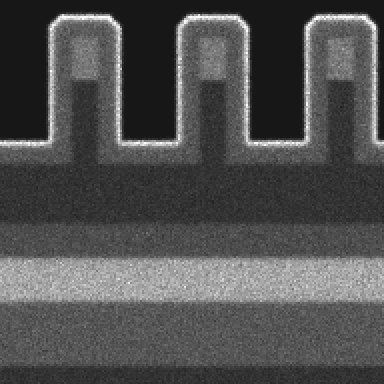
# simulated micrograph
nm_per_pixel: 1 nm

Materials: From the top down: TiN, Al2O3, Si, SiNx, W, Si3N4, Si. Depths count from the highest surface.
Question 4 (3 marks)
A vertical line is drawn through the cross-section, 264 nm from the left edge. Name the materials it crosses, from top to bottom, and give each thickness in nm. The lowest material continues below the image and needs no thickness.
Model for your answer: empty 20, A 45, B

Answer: empty 126, TiN 22, Si 60, SiNx 34, W 44, Si3N4 64, Si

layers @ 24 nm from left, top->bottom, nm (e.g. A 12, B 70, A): empty 126, TiN 22, Si 60, SiNx 34, W 44, Si3N4 64, Si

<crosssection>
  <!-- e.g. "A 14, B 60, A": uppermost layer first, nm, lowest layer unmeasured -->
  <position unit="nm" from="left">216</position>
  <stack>TiN 22, Al2O3 42, Si 144, SiNx 34, W 44, Si3N4 64, Si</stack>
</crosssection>